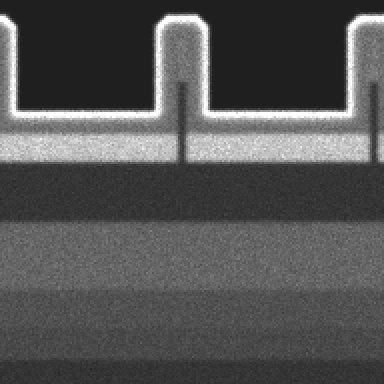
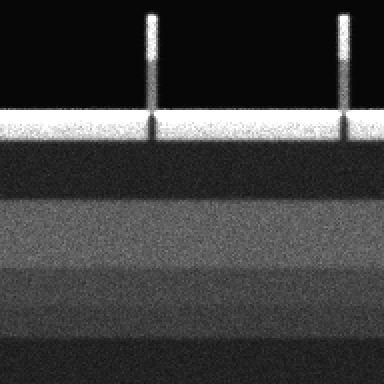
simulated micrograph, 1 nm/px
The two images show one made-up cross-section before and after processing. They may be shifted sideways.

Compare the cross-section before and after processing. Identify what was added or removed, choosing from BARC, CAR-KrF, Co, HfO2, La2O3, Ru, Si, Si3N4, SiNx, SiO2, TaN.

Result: SiO2 removed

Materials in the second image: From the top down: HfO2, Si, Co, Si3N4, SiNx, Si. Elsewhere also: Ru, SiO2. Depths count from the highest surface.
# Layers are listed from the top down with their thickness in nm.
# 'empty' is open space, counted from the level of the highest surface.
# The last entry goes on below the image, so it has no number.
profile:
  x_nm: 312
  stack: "empty 96, HfO2 28, Si 60, Co 68, Si3N4 38, SiNx 32, Si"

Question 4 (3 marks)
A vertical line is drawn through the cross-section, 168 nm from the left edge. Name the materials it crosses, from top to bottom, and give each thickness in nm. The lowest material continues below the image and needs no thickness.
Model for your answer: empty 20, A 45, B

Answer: empty 96, HfO2 28, Si 60, Co 68, Si3N4 38, SiNx 32, Si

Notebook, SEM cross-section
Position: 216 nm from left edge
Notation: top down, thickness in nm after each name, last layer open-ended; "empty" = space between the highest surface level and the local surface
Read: empty 96, HfO2 28, Si 60, Co 68, Si3N4 38, SiNx 32, Si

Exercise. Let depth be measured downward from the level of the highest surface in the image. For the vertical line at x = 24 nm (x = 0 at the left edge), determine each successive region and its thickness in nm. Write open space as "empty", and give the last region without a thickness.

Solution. empty 96, HfO2 28, Si 60, Co 68, Si3N4 38, SiNx 32, Si